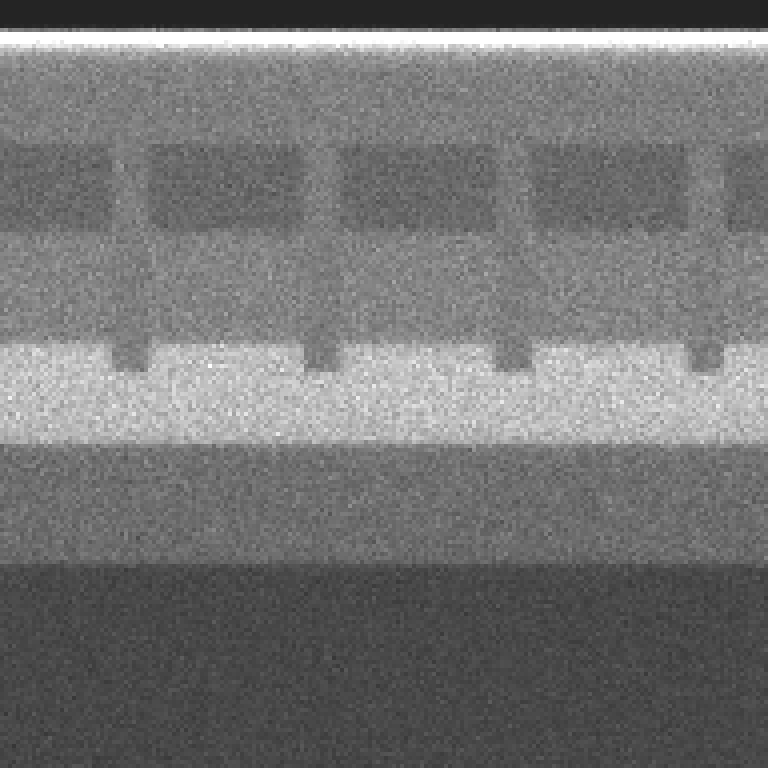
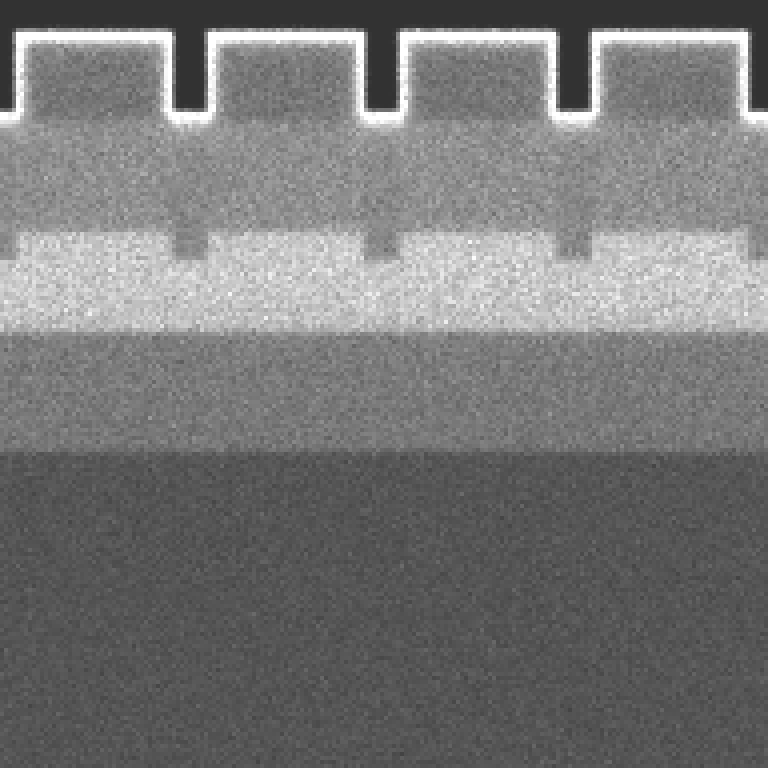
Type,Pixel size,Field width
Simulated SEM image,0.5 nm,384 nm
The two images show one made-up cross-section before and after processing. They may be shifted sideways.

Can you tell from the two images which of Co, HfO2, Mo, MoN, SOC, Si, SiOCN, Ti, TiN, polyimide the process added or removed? Yes, it removed SOC.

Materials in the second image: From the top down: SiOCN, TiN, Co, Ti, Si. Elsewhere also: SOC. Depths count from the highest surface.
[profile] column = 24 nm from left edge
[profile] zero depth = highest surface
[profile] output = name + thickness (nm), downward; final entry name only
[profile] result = SiOCN 44, TiN 56, Co 50, Ti 60, Si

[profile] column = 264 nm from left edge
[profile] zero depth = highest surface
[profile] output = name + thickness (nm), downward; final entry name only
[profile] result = SiOCN 44, TiN 56, Co 50, Ti 60, Si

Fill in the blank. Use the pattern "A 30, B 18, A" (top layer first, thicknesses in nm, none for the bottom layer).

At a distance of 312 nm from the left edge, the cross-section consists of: SiOCN 44, TiN 56, Co 50, Ti 60, Si